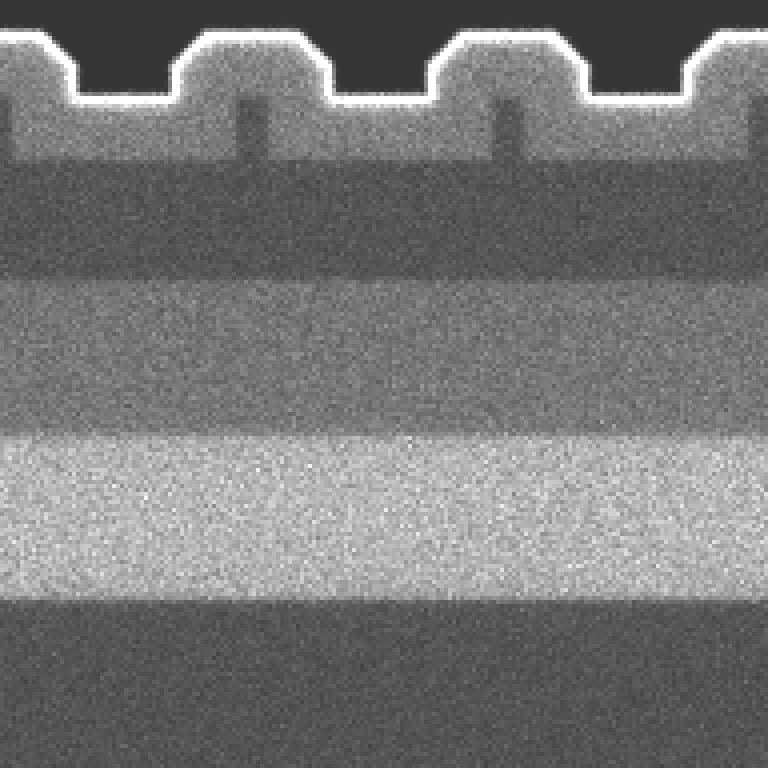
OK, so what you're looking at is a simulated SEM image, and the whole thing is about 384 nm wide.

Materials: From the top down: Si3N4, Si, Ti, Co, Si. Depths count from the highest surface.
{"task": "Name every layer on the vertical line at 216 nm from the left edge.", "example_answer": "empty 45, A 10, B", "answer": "empty 14, Si3N4 50, Si 60, Ti 78, Co 82, Si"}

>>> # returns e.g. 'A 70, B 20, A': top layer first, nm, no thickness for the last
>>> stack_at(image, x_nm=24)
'empty 4, Si3N4 60, Si 60, Ti 78, Co 82, Si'